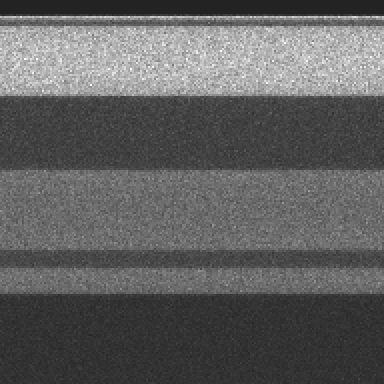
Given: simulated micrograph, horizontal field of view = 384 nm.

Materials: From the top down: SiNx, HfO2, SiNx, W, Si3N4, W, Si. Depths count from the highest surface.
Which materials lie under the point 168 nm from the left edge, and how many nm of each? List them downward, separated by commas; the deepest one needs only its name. SiNx 10, HfO2 70, SiNx 74, W 80, Si3N4 18, W 26, Si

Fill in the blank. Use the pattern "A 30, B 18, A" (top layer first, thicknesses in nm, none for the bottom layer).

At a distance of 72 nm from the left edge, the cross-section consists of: SiNx 10, HfO2 70, SiNx 74, W 80, Si3N4 18, W 26, Si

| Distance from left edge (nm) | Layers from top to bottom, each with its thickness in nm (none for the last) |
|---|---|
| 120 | SiNx 10, HfO2 70, SiNx 74, W 80, Si3N4 18, W 26, Si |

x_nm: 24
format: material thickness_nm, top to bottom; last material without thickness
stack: SiNx 10, HfO2 70, SiNx 74, W 80, Si3N4 18, W 26, Si